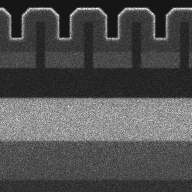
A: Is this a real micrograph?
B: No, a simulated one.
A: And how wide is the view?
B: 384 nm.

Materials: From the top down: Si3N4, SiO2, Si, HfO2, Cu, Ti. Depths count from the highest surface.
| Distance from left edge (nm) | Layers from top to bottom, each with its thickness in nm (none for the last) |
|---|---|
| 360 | Si3N4 28, Si 152, HfO2 86, Cu 78, Ti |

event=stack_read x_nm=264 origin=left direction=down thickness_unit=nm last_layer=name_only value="Si3N4 28, Si 152, HfO2 86, Cu 78, Ti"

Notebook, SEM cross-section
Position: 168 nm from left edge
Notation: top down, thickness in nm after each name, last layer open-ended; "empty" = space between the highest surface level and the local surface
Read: Si3N4 28, Si 152, HfO2 86, Cu 78, Ti